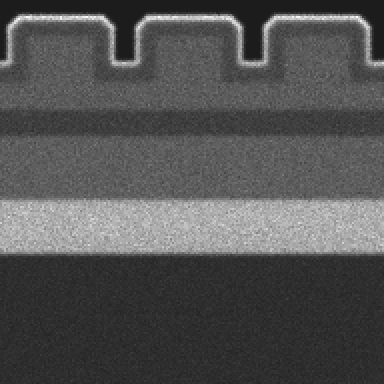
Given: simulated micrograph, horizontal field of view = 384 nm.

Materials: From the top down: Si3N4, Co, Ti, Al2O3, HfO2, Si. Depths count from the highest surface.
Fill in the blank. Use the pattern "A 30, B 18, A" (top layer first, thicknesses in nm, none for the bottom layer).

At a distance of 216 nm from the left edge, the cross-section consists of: Si3N4 20, Co 74, Ti 26, Al2O3 64, HfO2 54, Si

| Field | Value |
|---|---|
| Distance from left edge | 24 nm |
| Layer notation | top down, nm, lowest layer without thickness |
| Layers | Si3N4 66, Co 28, Ti 26, Al2O3 64, HfO2 54, Si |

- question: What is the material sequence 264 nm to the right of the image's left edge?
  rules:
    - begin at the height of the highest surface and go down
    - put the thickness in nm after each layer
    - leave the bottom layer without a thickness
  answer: empty 10, Si3N4 56, Co 28, Ti 26, Al2O3 64, HfO2 54, Si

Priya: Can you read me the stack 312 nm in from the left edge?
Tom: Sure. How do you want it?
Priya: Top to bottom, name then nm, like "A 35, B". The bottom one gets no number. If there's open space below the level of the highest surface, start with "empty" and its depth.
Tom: Si3N4 20, Co 74, Ti 26, Al2O3 64, HfO2 54, Si